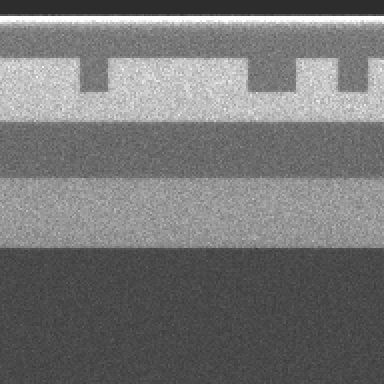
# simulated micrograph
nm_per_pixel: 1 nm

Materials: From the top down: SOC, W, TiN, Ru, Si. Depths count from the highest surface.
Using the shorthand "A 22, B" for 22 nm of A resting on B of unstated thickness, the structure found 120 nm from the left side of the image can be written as SOC 42, W 64, TiN 56, Ru 70, Si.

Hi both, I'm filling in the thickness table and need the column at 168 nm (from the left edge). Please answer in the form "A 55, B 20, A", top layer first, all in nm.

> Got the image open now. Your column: SOC 42, W 64, TiN 56, Ru 70, Si